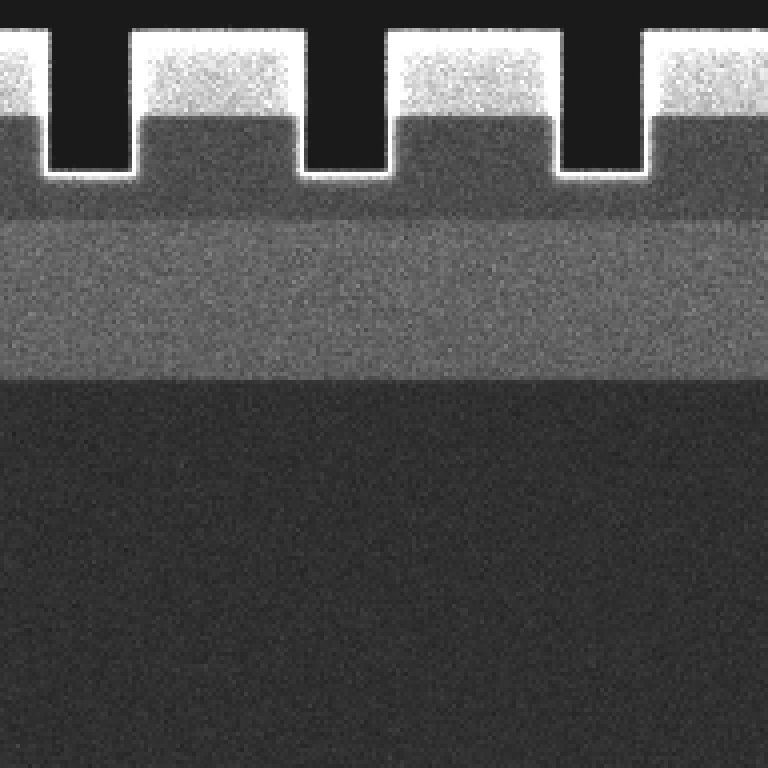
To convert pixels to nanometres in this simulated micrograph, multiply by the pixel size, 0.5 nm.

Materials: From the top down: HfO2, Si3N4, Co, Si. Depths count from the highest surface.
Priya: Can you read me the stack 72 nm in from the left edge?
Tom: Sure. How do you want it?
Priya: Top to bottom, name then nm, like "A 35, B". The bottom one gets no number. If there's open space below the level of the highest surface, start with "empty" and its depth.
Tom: HfO2 42, Si3N4 52, Co 80, Si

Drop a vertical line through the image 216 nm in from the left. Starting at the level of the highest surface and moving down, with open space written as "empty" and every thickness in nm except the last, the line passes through HfO2 42, Si3N4 52, Co 80, Si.